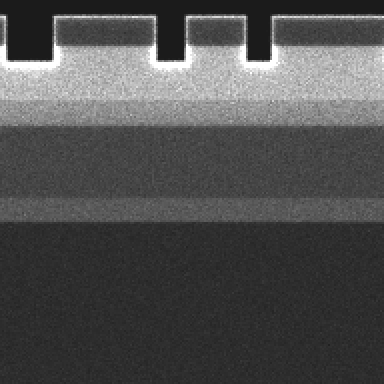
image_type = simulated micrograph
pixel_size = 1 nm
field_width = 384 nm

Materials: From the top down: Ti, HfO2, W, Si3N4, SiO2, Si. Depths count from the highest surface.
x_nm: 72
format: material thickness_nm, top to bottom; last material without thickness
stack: Ti 30, HfO2 54, W 26, Si3N4 72, SiO2 24, Si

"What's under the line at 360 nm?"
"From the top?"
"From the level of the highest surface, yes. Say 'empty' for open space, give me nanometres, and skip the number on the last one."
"Ti 30, HfO2 54, W 26, Si3N4 72, SiO2 24, Si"